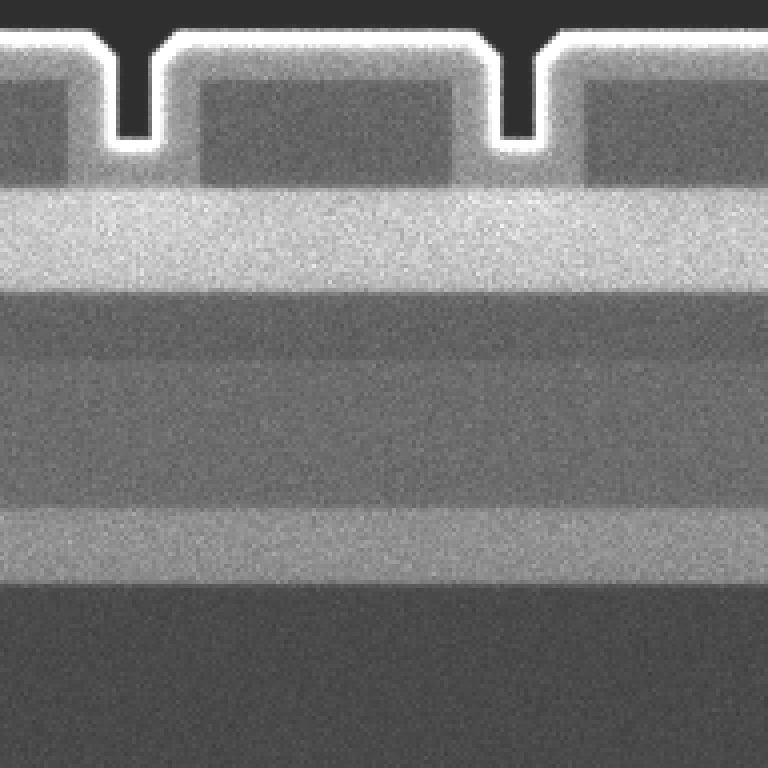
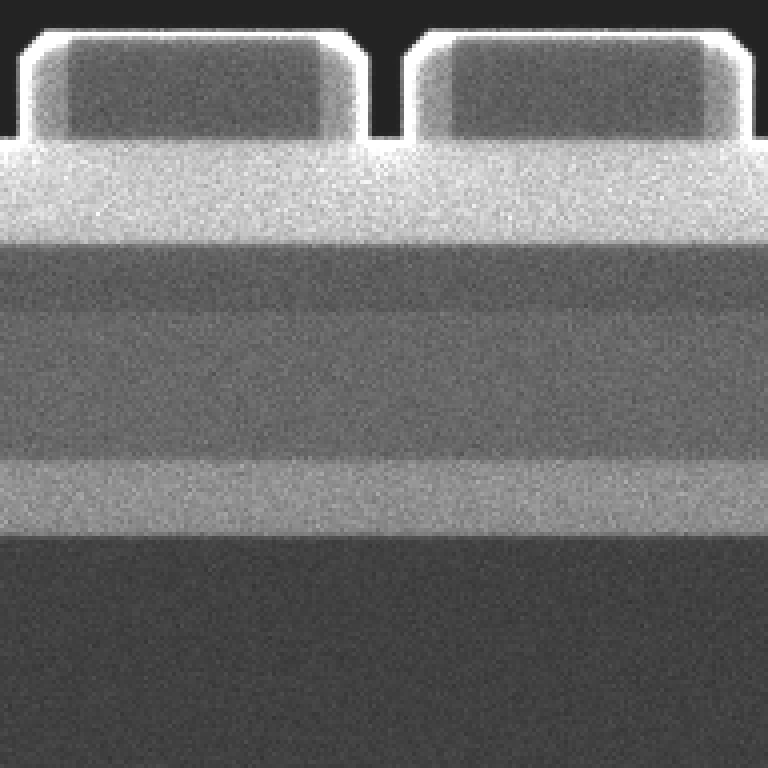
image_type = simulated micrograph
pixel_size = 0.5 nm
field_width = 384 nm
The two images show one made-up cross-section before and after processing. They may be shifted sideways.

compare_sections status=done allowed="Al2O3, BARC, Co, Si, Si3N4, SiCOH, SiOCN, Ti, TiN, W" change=removed material="Al2O3"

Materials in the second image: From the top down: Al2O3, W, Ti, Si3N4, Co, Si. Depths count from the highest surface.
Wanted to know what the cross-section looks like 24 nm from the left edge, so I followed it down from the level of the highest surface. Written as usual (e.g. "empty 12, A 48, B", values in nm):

Al2O3 54, W 52, Ti 34, Si3N4 74, Co 38, Si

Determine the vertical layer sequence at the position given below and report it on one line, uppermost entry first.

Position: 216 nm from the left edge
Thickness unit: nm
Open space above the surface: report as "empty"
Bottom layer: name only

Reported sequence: Al2O3 54, W 52, Ti 34, Si3N4 74, Co 38, Si